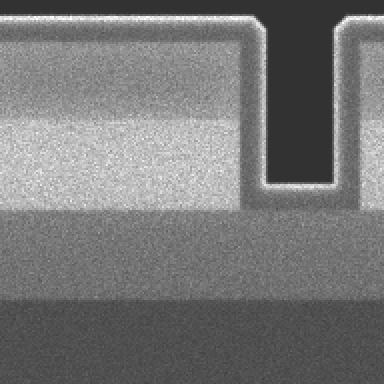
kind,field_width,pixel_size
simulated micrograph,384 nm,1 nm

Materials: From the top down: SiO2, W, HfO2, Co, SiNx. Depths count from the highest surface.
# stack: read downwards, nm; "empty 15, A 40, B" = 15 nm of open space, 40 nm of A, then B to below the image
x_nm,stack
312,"empty 168, SiO2 26, Co 90, SiNx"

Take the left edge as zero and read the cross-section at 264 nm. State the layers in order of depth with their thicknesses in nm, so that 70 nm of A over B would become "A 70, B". empty 12, SiO2 182, Co 90, SiNx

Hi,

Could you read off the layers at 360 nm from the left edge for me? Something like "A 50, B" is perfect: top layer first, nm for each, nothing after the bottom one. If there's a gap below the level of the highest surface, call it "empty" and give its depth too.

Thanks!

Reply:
SiO2 26, W 78, HfO2 90, Co 90, SiNx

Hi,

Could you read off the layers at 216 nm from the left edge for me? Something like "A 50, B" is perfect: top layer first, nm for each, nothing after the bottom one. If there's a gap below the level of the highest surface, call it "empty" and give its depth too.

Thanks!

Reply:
SiO2 26, W 78, HfO2 90, Co 90, SiNx